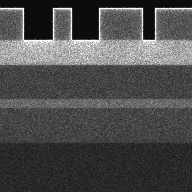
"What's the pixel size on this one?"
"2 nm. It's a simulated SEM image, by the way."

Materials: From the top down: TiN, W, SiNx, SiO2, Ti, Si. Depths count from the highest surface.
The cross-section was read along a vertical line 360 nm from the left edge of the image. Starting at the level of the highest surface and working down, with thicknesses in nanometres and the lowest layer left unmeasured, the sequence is TiN 64, W 50, SiNx 68, SiO2 18, Ti 70, Si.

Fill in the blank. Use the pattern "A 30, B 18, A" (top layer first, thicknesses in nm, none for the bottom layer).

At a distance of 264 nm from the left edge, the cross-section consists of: TiN 64, W 50, SiNx 68, SiO2 18, Ti 70, Si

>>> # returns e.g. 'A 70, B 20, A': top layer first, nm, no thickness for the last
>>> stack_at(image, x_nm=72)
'empty 64, W 50, SiNx 68, SiO2 18, Ti 70, Si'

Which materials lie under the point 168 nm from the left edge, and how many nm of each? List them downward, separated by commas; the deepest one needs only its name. empty 64, W 50, SiNx 68, SiO2 18, Ti 70, Si